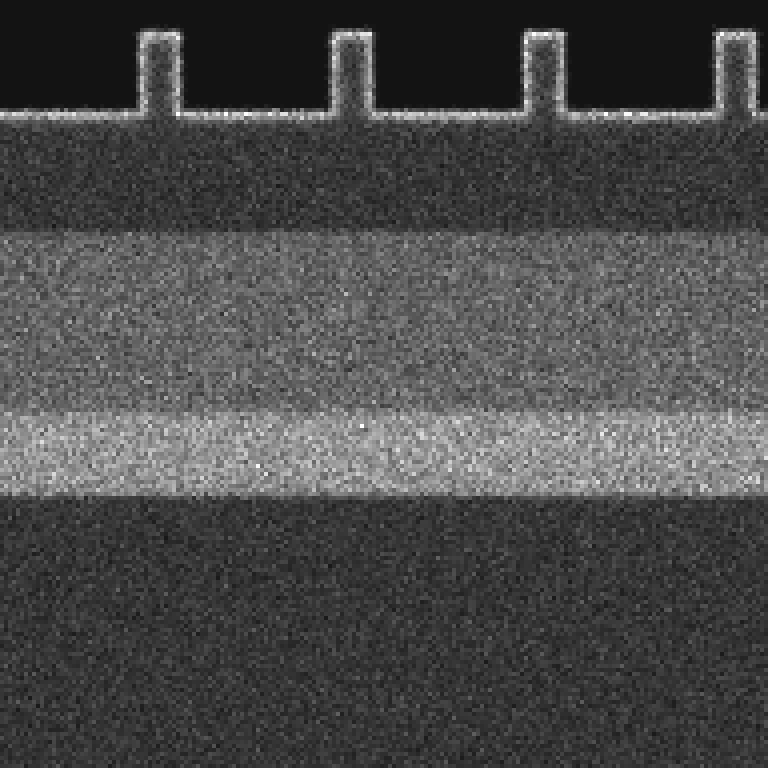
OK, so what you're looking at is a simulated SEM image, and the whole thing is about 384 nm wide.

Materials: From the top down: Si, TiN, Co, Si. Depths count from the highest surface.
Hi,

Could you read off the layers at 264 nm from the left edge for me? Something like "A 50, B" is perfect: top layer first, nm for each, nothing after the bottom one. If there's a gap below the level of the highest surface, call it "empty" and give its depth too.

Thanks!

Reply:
Si 100, TiN 90, Co 42, Si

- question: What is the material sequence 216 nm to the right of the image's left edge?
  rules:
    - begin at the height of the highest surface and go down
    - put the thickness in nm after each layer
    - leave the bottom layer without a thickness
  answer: empty 40, Si 60, TiN 90, Co 42, Si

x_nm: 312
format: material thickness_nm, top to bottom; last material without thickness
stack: empty 40, Si 60, TiN 90, Co 42, Si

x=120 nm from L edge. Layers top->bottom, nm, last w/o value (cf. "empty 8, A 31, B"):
empty 40, Si 60, TiN 90, Co 42, Si